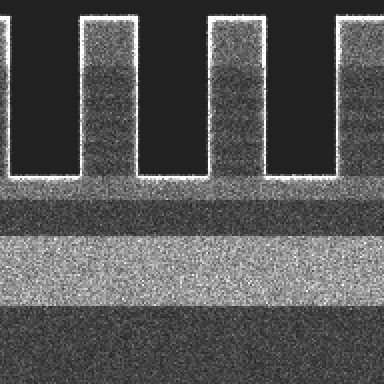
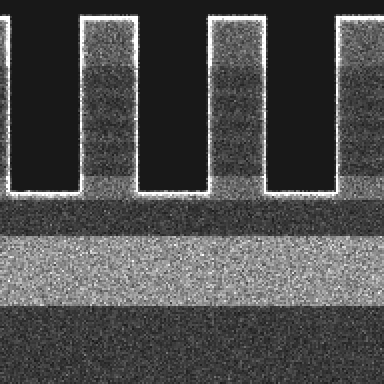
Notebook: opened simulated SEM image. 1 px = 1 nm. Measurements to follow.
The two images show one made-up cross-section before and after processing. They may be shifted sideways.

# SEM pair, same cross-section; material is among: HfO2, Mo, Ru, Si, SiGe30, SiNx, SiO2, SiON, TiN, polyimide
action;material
removed;TiN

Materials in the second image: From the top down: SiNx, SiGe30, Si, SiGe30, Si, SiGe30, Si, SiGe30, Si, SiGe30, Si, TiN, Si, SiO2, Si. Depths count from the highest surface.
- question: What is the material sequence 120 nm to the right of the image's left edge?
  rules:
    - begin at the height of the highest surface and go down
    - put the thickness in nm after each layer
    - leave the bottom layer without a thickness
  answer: SiNx 50, SiGe30 10, Si 12, SiGe30 10, Si 12, SiGe30 10, Si 12, SiGe30 10, Si 12, SiGe30 10, Si 12, TiN 24, Si 36, SiO2 70, Si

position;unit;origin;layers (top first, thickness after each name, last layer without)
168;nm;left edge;empty 176, TiN 8, Si 36, SiO2 70, Si